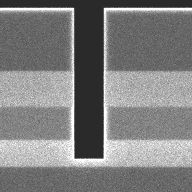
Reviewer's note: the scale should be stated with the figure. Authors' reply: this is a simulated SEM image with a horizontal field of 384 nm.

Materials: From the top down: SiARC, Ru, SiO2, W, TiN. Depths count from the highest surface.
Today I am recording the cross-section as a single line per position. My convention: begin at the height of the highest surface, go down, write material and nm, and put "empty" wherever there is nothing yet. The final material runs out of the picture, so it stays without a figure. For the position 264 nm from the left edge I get SiARC 126, Ru 72, SiO2 66, W 54, TiN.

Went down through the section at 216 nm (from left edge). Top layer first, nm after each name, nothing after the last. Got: SiARC 126, Ru 72, SiO2 66, W 54, TiN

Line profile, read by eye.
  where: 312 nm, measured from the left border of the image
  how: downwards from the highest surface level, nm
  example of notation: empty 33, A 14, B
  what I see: SiARC 126, Ru 72, SiO2 66, W 54, TiN